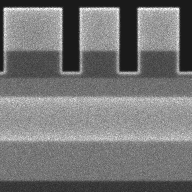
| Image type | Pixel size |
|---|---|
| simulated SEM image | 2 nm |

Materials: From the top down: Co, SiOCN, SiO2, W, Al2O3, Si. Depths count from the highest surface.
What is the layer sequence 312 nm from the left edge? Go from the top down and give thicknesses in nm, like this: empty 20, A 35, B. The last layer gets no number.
Co 86, SiOCN 54, SiO2 38, W 88, Al2O3 80, Si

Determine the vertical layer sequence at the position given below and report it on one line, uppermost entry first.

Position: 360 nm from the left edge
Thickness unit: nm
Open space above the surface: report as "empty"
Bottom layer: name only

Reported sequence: empty 128, SiOCN 12, SiO2 38, W 88, Al2O3 80, Si